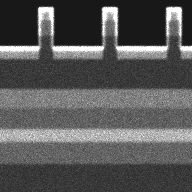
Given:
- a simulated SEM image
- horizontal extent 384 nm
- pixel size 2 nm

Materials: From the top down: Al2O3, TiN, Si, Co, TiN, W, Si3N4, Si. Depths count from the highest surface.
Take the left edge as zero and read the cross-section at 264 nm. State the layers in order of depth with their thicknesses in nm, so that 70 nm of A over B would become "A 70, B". empty 78, Al2O3 24, Si 60, Co 38, TiN 42, W 26, Si3N4 44, Si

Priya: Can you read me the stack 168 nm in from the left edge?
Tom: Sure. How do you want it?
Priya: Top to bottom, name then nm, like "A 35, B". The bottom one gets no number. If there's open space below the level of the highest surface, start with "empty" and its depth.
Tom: empty 78, Al2O3 24, Si 60, Co 38, TiN 42, W 26, Si3N4 44, Si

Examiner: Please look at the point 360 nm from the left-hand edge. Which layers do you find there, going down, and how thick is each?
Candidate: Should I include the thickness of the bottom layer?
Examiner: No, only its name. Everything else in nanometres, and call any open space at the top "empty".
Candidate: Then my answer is Al2O3 24, TiN 32, Si 106, Co 38, TiN 42, W 26, Si3N4 44, Si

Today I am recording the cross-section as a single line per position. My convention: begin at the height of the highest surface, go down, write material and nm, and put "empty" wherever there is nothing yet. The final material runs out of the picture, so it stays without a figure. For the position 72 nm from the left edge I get empty 78, Al2O3 24, Si 60, Co 38, TiN 42, W 26, Si3N4 44, Si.